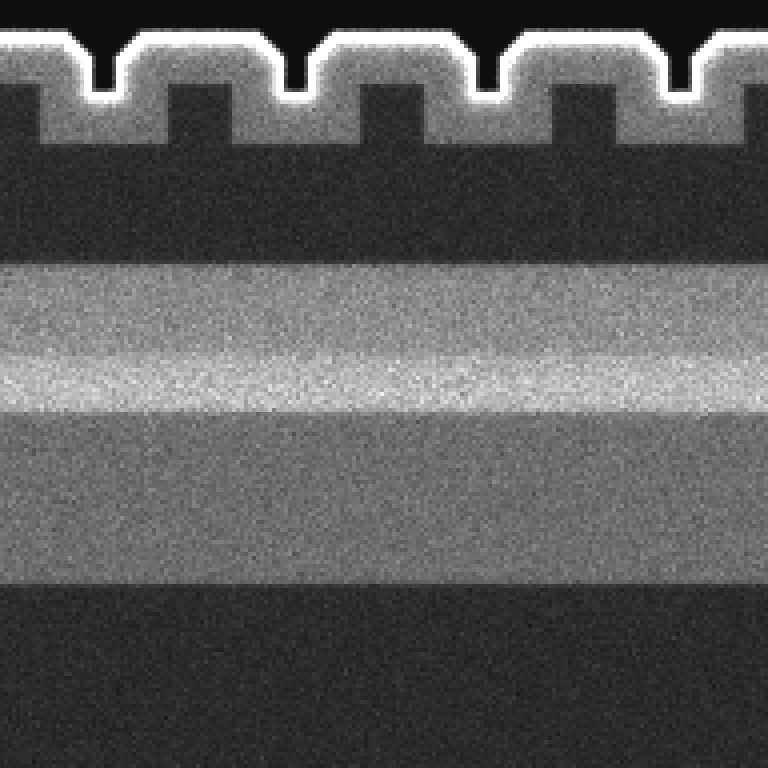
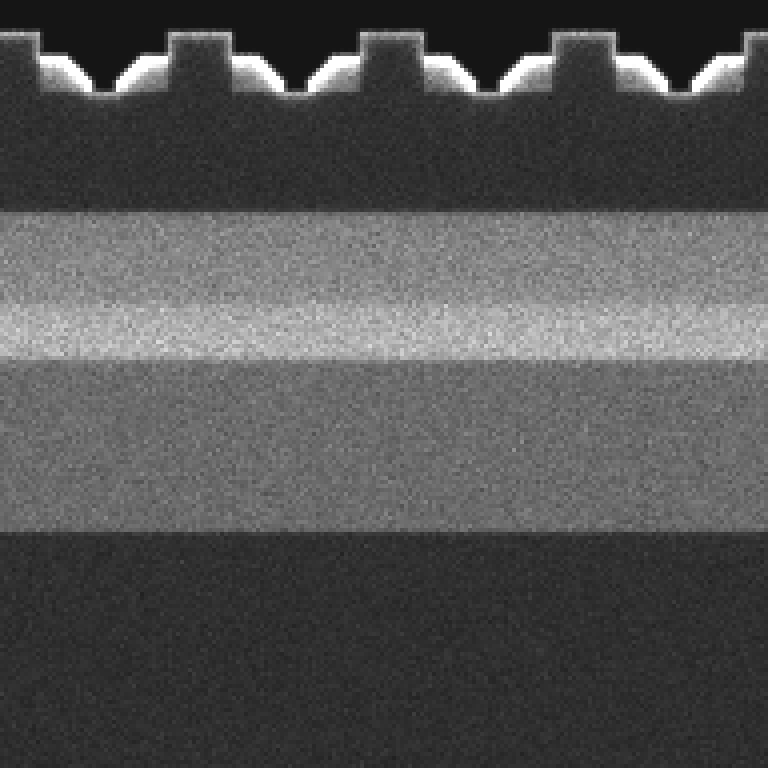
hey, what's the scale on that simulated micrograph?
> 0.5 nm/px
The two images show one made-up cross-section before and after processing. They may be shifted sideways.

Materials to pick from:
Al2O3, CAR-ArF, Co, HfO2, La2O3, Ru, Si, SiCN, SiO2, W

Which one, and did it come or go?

Al2O3 - removed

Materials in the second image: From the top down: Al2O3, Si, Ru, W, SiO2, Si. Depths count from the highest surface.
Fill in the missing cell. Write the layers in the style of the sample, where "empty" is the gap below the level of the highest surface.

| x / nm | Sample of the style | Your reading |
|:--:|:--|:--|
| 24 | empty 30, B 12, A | empty 12, Al2O3 18, Si 60, Ru 46, W 28, SiO2 86, Si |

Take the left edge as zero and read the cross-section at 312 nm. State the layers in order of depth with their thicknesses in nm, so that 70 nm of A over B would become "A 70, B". empty 12, Al2O3 18, Si 60, Ru 46, W 28, SiO2 86, Si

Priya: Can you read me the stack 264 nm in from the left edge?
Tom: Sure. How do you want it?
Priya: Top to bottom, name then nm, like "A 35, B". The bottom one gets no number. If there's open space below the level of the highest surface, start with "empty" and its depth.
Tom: empty 12, Al2O3 18, Si 60, Ru 46, W 28, SiO2 86, Si